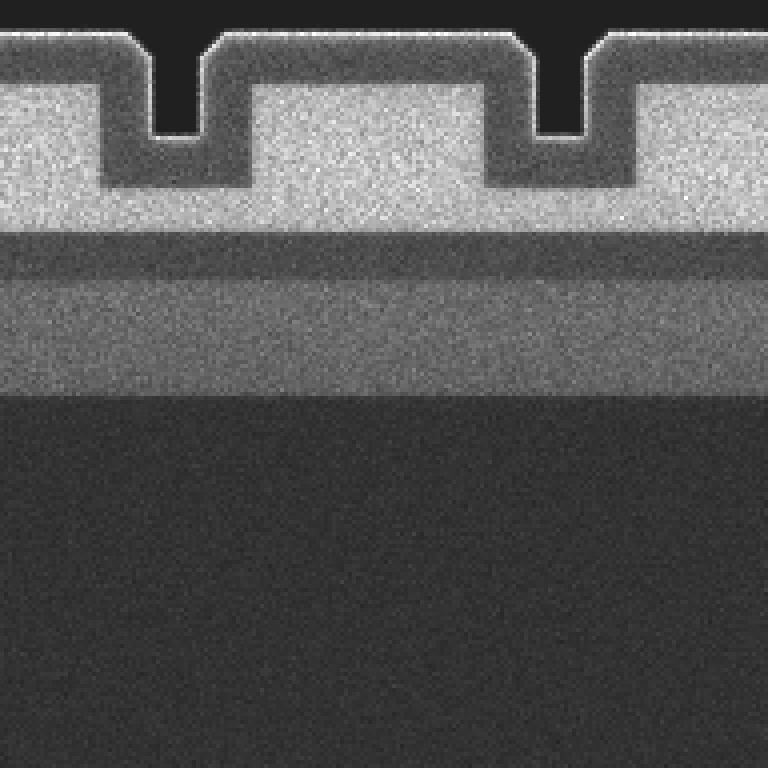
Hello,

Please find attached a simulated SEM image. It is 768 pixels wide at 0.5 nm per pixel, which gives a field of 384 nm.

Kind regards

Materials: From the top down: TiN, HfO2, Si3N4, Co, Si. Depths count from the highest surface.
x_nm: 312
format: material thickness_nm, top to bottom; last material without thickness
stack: TiN 78, HfO2 22, Si3N4 24, Co 58, Si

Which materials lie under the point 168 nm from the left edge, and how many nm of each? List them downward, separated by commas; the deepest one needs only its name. TiN 26, HfO2 74, Si3N4 24, Co 58, Si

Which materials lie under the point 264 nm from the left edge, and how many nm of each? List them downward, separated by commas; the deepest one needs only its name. empty 10, TiN 68, HfO2 22, Si3N4 24, Co 58, Si